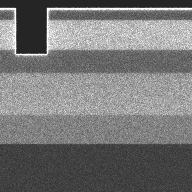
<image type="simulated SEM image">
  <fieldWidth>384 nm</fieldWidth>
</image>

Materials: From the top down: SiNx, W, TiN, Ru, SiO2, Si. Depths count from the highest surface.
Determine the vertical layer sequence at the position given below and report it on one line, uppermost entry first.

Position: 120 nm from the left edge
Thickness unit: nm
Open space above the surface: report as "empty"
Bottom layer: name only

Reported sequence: SiNx 24, W 60, TiN 46, Ru 84, SiO2 58, Si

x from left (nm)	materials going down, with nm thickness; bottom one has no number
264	SiNx 24, W 60, TiN 46, Ru 84, SiO2 58, Si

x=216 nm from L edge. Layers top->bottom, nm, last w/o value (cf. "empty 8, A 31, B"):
SiNx 24, W 60, TiN 46, Ru 84, SiO2 58, Si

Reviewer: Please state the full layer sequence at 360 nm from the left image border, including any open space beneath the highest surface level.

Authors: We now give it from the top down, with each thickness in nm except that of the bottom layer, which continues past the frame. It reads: SiNx 24, W 60, TiN 46, Ru 84, SiO2 58, Si